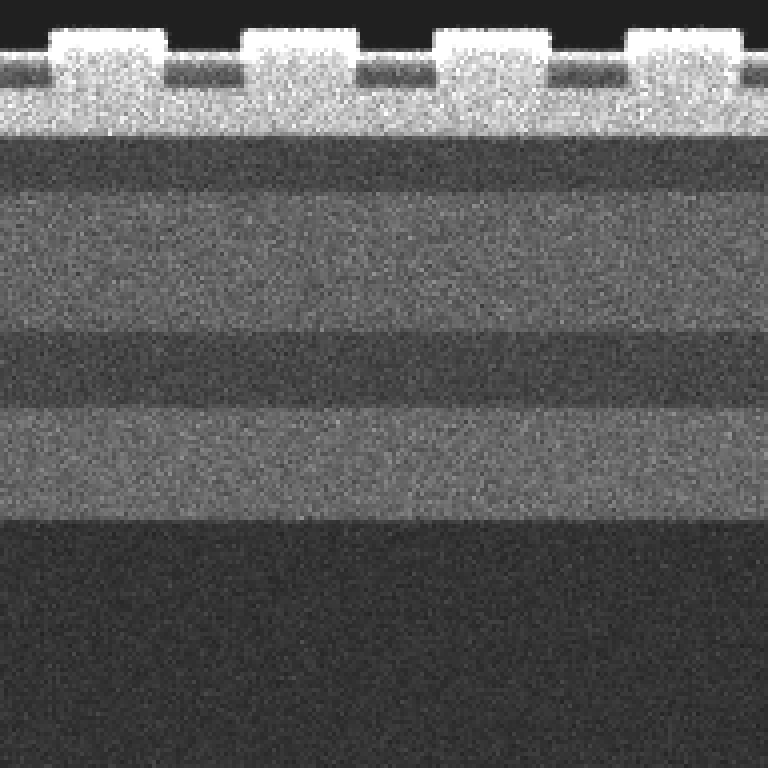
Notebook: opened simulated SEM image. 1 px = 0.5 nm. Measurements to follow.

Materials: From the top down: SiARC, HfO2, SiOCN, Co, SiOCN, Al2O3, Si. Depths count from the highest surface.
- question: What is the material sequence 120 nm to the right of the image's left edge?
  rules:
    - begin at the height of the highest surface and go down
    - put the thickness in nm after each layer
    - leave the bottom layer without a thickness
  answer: empty 10, SiARC 18, HfO2 24, SiOCN 28, Co 70, SiOCN 38, Al2O3 56, Si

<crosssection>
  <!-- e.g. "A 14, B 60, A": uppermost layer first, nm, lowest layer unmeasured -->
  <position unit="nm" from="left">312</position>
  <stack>empty 10, SiARC 18, HfO2 24, SiOCN 28, Co 70, SiOCN 38, Al2O3 56, Si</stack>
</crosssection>